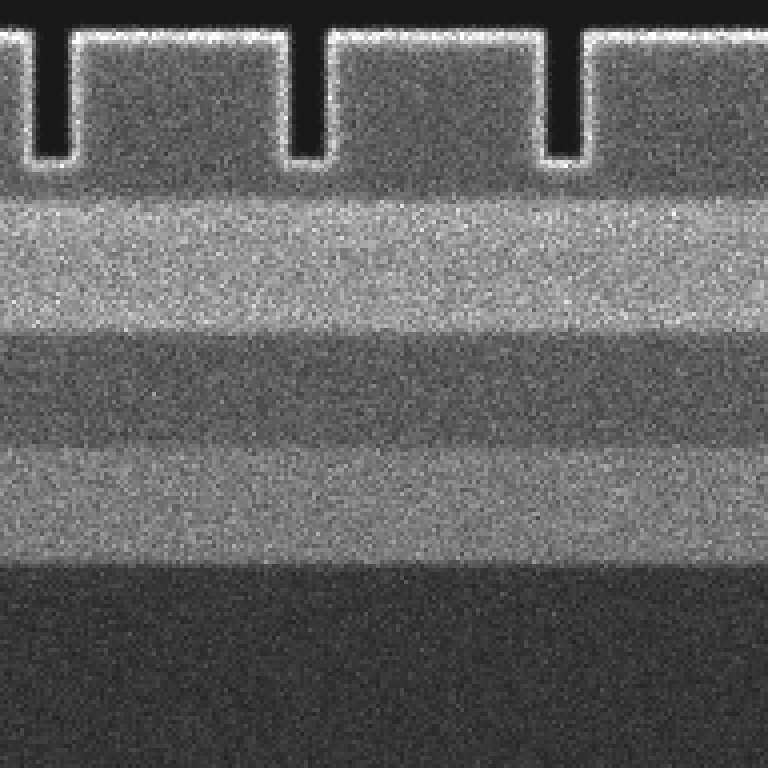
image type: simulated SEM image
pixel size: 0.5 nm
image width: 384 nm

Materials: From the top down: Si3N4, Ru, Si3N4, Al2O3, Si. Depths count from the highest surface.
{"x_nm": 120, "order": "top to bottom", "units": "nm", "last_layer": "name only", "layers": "Si3N4 84, Ru 66, Si3N4 58, Al2O3 58, Si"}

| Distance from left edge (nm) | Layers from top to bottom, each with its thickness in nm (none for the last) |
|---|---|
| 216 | Si3N4 84, Ru 66, Si3N4 58, Al2O3 58, Si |